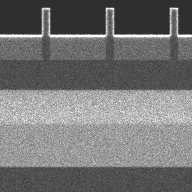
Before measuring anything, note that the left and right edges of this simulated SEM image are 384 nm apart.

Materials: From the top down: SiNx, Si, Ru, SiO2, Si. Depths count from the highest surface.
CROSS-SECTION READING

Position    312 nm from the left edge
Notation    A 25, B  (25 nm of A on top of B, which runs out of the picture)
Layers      empty 54, SiNx 50, Si 60, Ru 68, SiO2 86, Si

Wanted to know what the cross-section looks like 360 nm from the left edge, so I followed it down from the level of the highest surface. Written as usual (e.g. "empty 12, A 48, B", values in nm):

empty 54, SiNx 50, Si 60, Ru 68, SiO2 86, Si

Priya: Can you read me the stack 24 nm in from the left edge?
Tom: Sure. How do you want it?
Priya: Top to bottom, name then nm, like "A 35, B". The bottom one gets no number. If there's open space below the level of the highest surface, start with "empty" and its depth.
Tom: empty 54, SiNx 50, Si 60, Ru 68, SiO2 86, Si